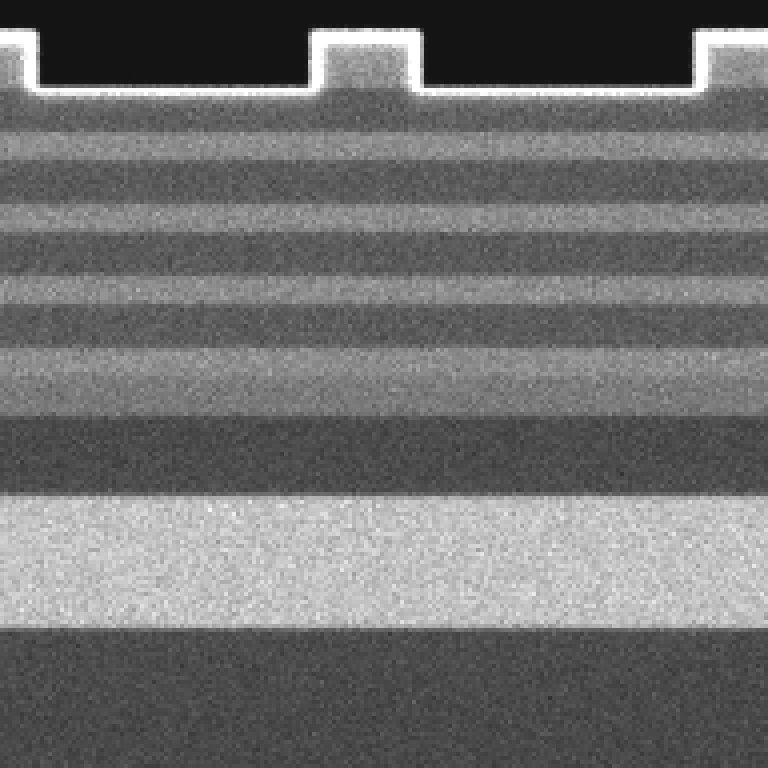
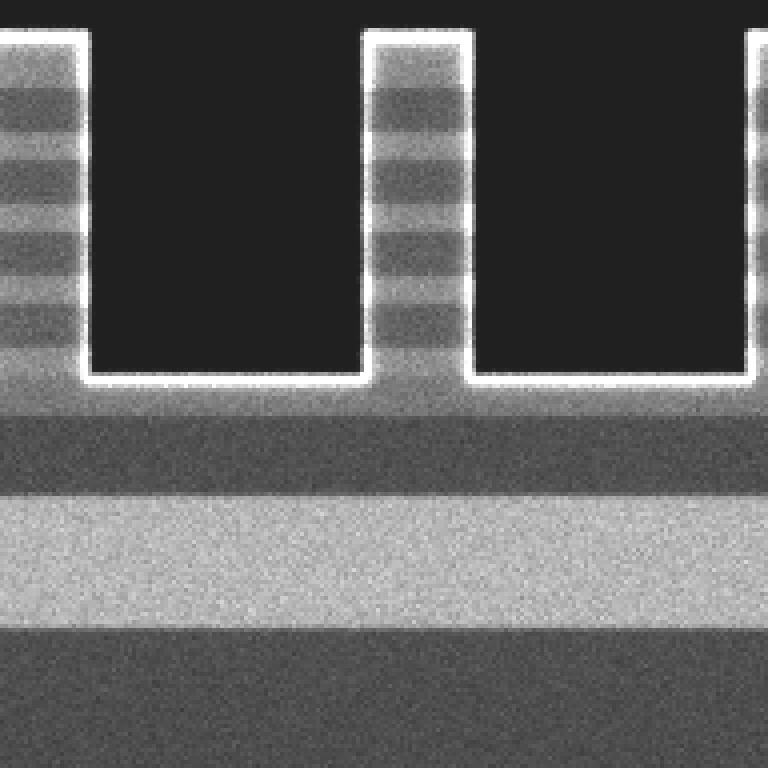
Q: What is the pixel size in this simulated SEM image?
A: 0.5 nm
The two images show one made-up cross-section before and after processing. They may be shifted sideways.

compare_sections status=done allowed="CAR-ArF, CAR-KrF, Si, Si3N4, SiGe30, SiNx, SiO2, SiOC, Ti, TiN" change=removed material="SiGe30 and TiN"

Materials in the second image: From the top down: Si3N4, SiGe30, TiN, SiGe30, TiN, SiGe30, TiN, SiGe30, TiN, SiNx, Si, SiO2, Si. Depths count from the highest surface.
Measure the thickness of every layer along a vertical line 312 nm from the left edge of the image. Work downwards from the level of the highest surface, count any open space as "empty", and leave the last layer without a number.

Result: empty 172, SiNx 20, Si 40, SiO2 66, Si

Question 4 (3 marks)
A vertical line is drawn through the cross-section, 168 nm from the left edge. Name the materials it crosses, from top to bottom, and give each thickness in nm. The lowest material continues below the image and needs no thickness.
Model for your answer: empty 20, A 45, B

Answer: empty 172, SiNx 20, Si 40, SiO2 66, Si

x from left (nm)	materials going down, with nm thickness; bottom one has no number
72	empty 172, SiNx 20, Si 40, SiO2 66, Si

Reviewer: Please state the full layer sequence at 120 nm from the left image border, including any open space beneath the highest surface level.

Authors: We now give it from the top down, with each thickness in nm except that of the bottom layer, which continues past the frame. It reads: empty 172, SiNx 20, Si 40, SiO2 66, Si